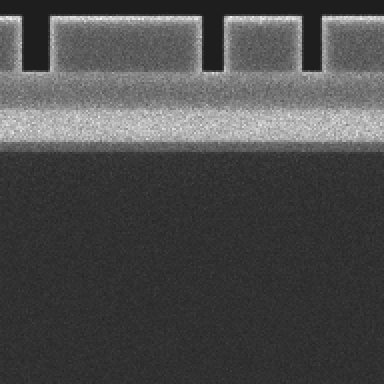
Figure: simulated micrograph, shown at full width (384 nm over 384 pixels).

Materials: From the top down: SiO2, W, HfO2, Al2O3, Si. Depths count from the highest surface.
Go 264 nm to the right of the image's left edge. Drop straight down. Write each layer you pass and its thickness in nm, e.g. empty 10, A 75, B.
SiO2 56, W 38, HfO2 32, Al2O3 10, Si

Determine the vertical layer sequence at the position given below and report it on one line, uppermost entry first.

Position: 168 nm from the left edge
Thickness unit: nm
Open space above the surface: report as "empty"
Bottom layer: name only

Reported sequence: SiO2 56, W 38, HfO2 32, Al2O3 10, Si